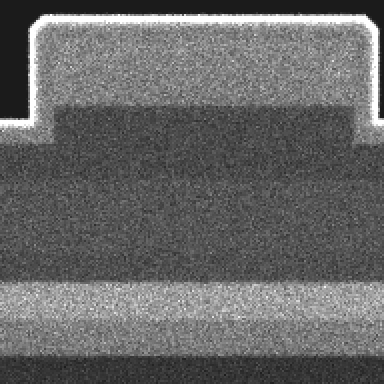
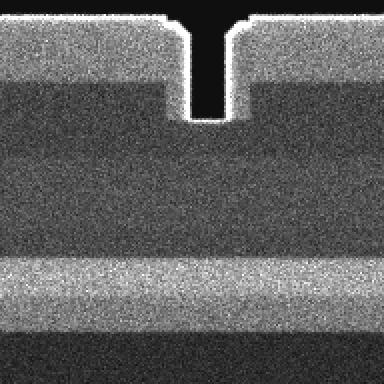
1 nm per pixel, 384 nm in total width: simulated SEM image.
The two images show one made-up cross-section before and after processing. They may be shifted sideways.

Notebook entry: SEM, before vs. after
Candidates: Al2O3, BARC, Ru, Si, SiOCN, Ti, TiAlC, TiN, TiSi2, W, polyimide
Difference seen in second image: Al2O3 removed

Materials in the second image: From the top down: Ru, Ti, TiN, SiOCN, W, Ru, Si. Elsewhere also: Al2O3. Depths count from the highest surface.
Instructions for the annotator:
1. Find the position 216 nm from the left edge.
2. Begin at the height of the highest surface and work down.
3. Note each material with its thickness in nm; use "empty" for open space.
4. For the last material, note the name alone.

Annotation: empty 104, Ti 36, TiN 74, SiOCN 28, W 38, Ru 36, Si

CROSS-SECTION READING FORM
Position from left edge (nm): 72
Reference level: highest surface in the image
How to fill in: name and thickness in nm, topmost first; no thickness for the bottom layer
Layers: Ru 66, Ti 74, TiN 74, SiOCN 28, W 38, Ru 36, Si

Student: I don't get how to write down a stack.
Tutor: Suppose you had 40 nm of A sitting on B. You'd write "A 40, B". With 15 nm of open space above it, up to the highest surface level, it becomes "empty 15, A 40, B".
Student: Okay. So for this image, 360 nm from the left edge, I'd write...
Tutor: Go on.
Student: Ru 66, Ti 74, TiN 74, SiOCN 28, W 38, Ru 36, Si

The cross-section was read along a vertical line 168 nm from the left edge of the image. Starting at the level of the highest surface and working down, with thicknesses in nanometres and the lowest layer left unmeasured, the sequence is empty 6, Al2O3 98, Ti 36, TiN 74, SiOCN 28, W 38, Ru 36, Si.